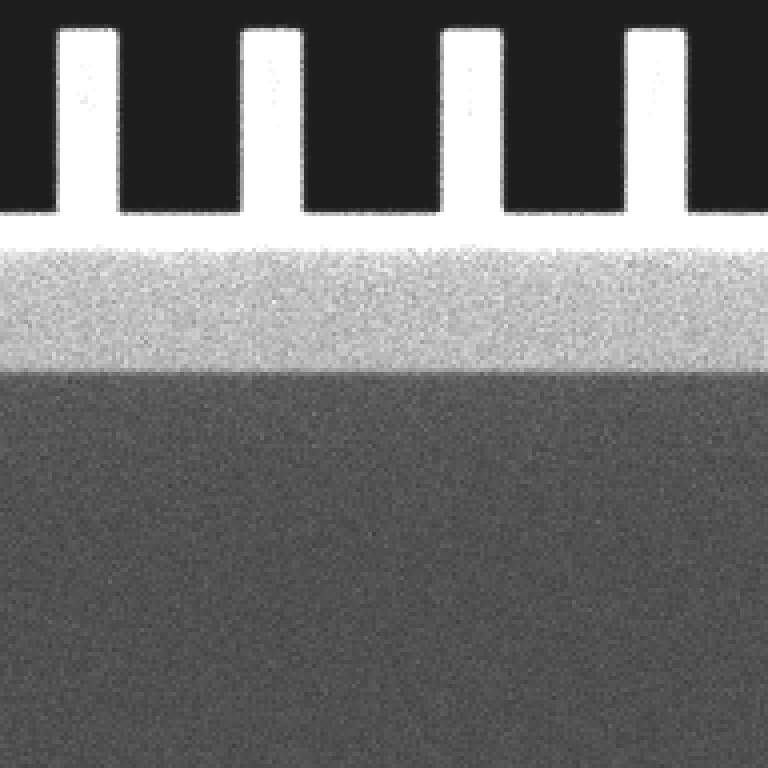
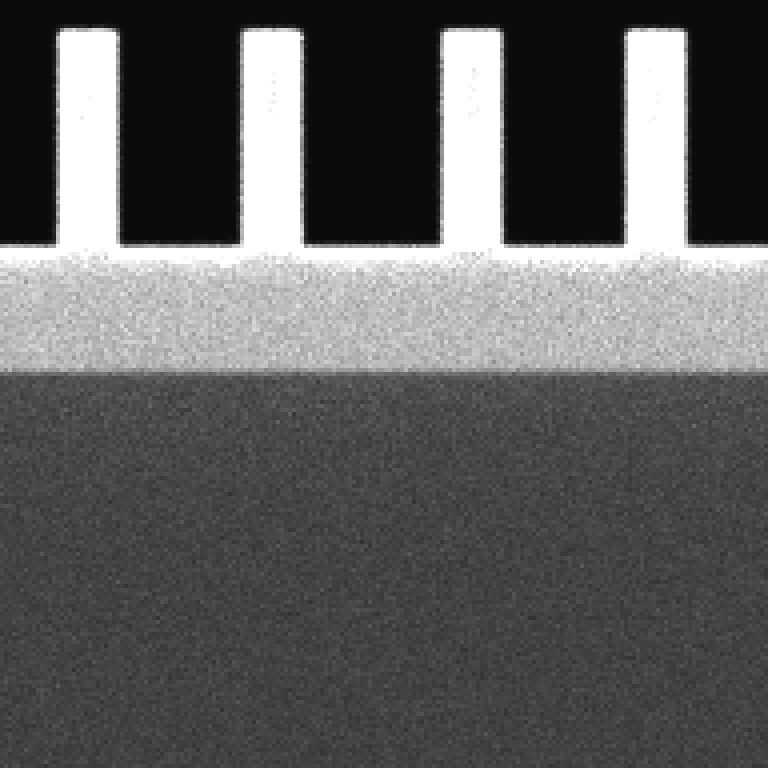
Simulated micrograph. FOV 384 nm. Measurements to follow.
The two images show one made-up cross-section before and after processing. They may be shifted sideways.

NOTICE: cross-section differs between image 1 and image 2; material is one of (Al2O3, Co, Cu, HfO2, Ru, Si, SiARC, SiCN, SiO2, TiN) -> removed: Co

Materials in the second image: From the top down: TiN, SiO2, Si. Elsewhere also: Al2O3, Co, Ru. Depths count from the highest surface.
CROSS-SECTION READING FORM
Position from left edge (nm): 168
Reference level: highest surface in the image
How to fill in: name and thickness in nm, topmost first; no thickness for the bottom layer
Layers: empty 108, TiN 12, SiO2 50, Si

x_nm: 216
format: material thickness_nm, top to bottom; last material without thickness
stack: empty 108, TiN 12, SiO2 50, Si